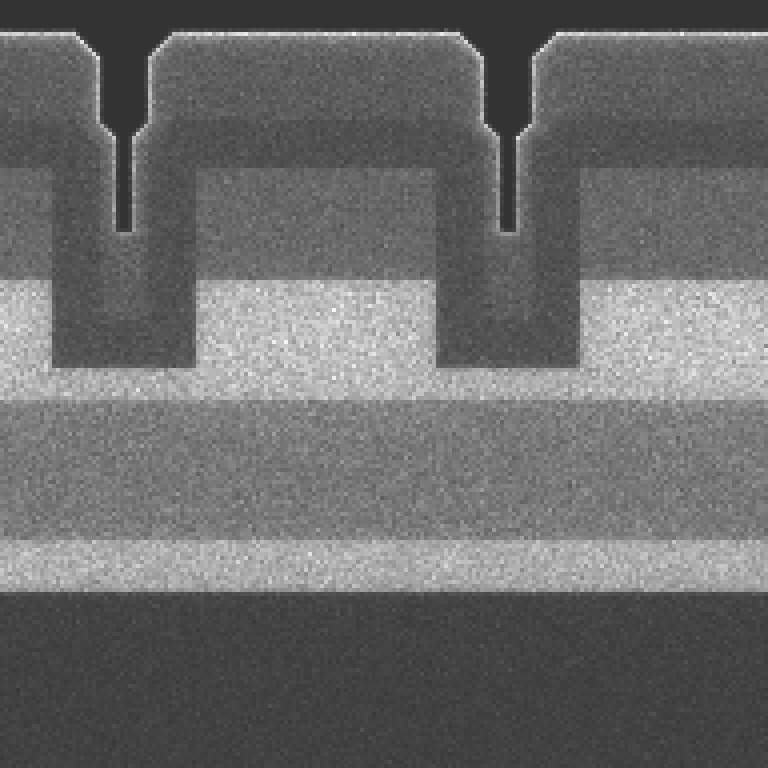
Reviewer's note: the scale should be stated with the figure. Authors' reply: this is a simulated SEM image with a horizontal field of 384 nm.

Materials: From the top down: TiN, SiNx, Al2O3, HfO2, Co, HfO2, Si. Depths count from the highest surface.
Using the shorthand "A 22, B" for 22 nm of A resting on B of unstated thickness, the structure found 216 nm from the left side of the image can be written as TiN 44, SiNx 24, Al2O3 56, HfO2 60, Co 70, HfO2 26, Si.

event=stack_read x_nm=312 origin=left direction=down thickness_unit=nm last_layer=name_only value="TiN 44, SiNx 24, Al2O3 56, HfO2 60, Co 70, HfO2 26, Si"